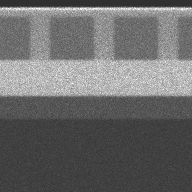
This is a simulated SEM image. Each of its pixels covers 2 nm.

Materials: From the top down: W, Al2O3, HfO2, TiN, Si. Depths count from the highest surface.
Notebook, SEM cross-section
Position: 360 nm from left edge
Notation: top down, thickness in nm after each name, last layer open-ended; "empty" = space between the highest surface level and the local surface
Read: W 18, Al2O3 86, HfO2 72, TiN 46, Si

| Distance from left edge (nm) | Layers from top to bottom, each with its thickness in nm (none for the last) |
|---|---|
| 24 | W 18, Al2O3 86, HfO2 72, TiN 46, Si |